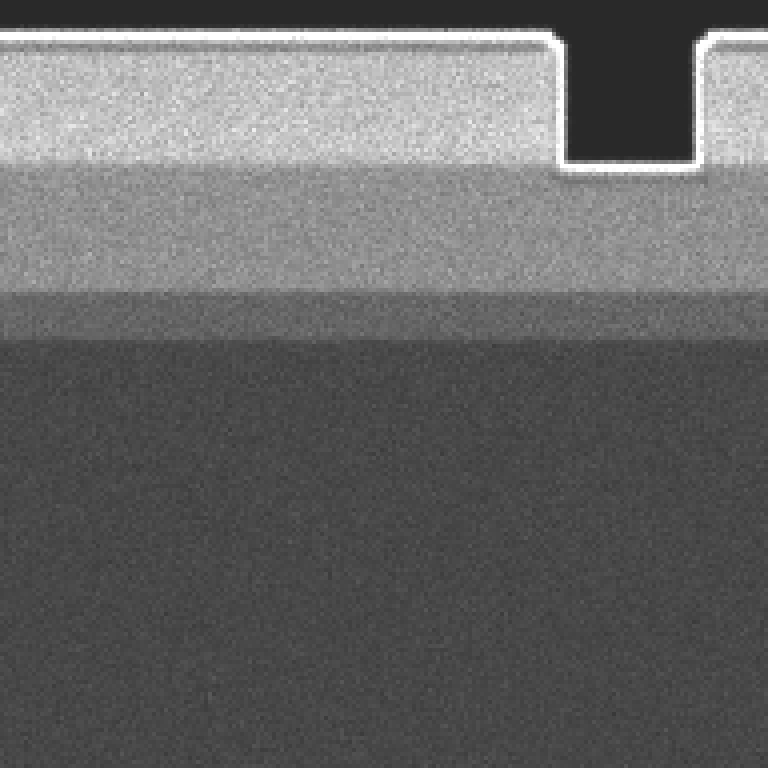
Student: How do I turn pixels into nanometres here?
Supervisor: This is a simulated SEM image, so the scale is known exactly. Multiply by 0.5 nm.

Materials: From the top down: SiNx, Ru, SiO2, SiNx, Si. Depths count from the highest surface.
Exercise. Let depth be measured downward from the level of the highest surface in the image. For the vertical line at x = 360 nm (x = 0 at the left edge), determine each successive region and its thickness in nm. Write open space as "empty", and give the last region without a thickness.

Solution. SiNx 10, Ru 56, SiO2 64, SiNx 24, Si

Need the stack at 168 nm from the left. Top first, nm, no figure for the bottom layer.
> SiNx 10, Ru 56, SiO2 64, SiNx 24, Si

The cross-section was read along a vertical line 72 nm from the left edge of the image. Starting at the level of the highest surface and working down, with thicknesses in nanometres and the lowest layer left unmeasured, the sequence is SiNx 10, Ru 56, SiO2 64, SiNx 24, Si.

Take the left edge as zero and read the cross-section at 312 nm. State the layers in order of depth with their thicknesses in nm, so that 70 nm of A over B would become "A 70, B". empty 66, SiNx 10, SiO2 54, SiNx 24, Si